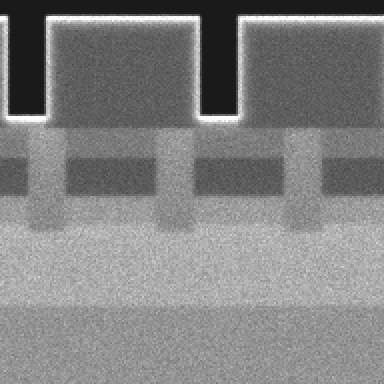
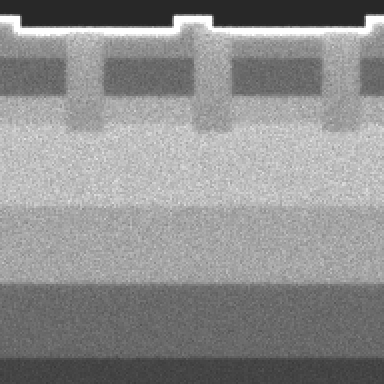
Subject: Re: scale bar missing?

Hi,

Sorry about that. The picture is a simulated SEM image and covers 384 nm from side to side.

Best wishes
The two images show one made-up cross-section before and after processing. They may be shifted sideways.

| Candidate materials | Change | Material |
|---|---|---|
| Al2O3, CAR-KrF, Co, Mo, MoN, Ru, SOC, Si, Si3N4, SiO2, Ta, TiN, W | removed | SOC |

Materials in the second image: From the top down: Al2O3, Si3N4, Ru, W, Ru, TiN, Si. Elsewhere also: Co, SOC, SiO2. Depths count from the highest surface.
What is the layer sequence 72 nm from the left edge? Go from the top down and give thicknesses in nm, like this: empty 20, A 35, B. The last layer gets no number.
empty 12, Co 104, W 74, Ru 78, TiN 74, Si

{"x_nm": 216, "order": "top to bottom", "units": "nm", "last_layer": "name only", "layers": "empty 12, Co 104, W 74, Ru 78, TiN 74, Si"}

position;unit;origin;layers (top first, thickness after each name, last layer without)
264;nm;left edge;empty 12, Al2O3 30, Si3N4 38, Ru 28, W 82, Ru 78, TiN 74, Si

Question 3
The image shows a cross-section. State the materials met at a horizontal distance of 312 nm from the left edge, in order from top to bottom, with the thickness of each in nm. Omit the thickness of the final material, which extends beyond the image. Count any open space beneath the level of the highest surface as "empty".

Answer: empty 12, Al2O3 30, Si3N4 38, Ru 28, W 82, Ru 78, TiN 74, Si